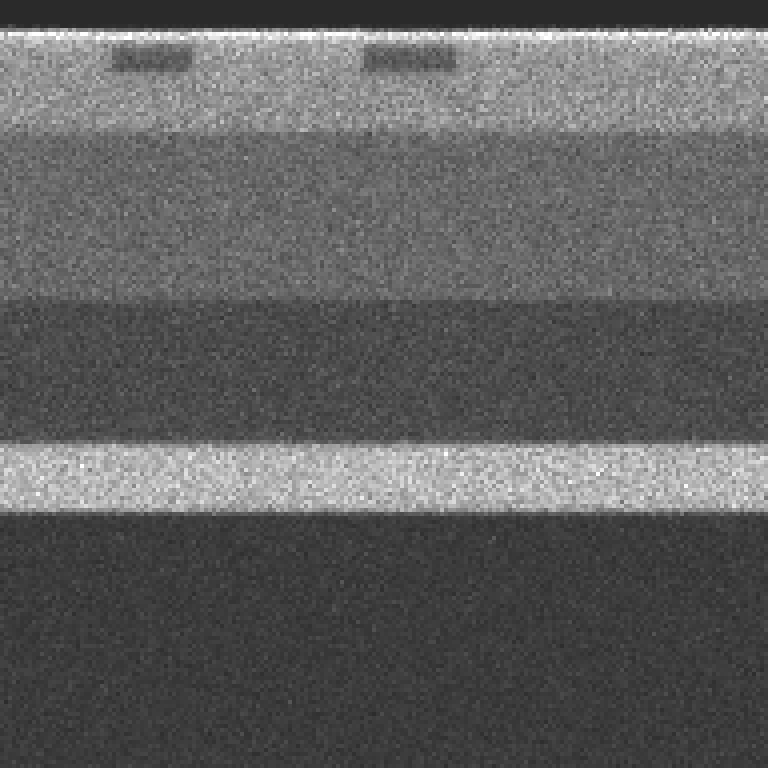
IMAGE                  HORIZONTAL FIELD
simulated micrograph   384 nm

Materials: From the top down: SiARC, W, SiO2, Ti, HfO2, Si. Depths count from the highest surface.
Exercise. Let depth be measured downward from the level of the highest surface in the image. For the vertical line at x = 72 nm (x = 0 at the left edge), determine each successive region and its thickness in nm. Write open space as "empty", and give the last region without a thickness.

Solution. SiARC 20, W 30, SiO2 84, Ti 72, HfO2 34, Si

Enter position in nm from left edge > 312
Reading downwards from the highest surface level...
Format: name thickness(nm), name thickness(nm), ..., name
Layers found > W 50, SiO2 84, Ti 72, HfO2 34, Si